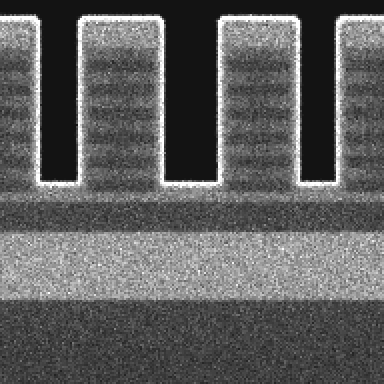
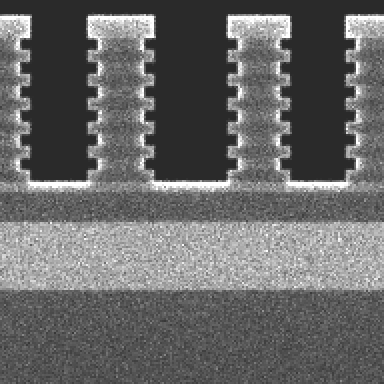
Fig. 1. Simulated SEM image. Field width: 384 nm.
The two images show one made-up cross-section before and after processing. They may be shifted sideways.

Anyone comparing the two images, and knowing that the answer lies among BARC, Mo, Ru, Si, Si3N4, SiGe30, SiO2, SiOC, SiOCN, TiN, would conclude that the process removed SiOCN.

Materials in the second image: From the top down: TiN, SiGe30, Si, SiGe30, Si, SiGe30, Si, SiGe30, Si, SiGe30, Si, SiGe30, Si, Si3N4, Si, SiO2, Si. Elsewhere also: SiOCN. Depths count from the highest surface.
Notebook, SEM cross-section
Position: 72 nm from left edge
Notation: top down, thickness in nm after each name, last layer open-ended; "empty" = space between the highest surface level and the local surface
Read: empty 166, Si3N4 10, Si 30, SiO2 68, Si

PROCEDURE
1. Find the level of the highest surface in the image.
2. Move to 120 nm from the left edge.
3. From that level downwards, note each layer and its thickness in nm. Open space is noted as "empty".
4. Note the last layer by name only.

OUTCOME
TiN 22, SiGe30 12, Si 12, SiGe30 12, Si 12, SiGe30 12, Si 12, SiGe30 12, Si 12, SiGe30 12, Si 12, SiGe30 12, Si 12, Si3N4 10, Si 30, SiO2 68, Si